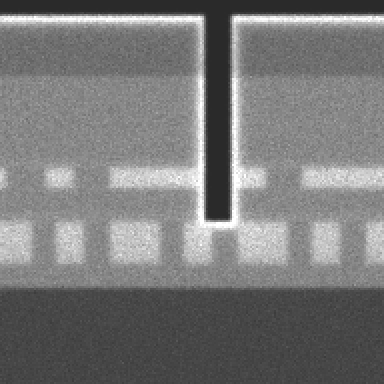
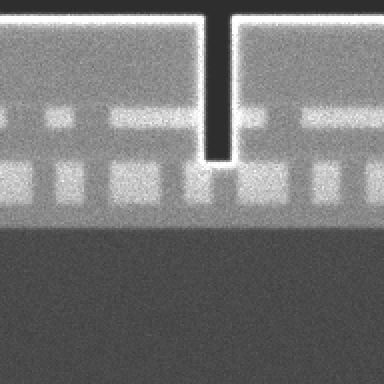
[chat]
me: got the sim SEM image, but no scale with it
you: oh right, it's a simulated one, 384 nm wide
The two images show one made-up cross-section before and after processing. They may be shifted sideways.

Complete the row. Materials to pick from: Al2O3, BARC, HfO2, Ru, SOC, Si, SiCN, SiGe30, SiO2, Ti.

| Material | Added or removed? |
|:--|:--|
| SOC | removed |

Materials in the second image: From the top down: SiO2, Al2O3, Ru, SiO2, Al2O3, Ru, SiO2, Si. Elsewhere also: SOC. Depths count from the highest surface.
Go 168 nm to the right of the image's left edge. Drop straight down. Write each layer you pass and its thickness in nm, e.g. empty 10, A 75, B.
SiO2 84, Al2O3 8, Ru 20, SiO2 24, Al2O3 10, SiO2 66, Si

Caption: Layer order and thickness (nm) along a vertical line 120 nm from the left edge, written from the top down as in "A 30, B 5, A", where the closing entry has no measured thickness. SiO2 84, Al2O3 8, Ru 20, SiO2 24, Al2O3 10, Ru 42, SiO2 24, Si